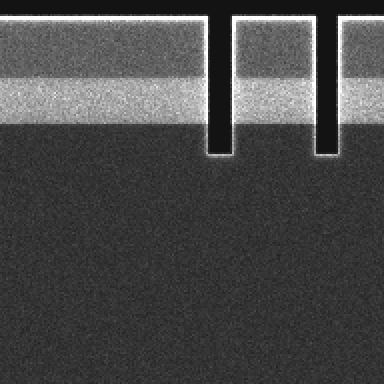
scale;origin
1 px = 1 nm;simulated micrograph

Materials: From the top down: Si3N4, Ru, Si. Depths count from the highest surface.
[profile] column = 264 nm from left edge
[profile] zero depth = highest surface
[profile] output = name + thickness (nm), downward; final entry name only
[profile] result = Si3N4 62, Ru 46, Si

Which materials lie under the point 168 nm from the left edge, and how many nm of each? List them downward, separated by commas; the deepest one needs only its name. Si3N4 62, Ru 46, Si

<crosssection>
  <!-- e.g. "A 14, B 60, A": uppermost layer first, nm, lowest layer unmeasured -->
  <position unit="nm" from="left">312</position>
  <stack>Si3N4 62, Ru 46, Si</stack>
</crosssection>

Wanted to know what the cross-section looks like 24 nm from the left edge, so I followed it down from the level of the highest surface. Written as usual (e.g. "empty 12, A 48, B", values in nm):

Si3N4 62, Ru 46, Si